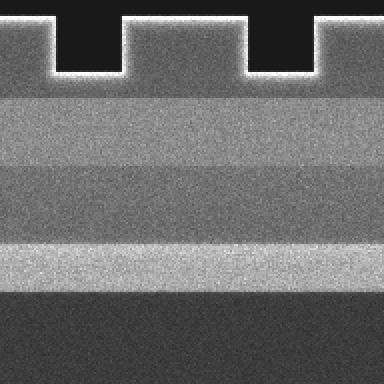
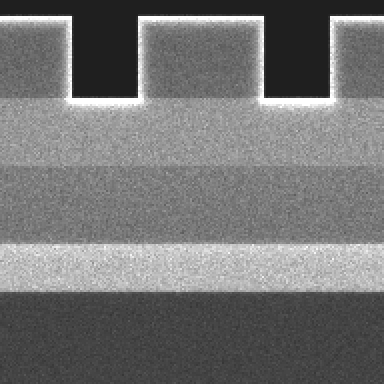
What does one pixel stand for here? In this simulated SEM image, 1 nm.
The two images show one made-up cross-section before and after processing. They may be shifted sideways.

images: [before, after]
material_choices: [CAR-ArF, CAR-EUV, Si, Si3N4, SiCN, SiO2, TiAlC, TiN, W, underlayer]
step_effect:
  removed: underlayer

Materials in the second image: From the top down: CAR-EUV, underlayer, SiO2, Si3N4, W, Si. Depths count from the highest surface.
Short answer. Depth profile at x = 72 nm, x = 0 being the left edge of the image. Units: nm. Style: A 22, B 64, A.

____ empty 82, SiO2 68, Si3N4 78, W 48, Si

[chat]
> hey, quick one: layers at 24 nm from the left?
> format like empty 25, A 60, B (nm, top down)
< CAR-EUV 56, underlayer 26, SiO2 68, Si3N4 78, W 48, Si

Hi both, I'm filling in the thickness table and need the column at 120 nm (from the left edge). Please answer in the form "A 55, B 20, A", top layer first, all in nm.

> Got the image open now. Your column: empty 82, SiO2 68, Si3N4 78, W 48, Si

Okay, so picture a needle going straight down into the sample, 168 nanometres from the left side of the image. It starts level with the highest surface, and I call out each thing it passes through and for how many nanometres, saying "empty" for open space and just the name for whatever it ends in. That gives CAR-EUV 56, underlayer 26, SiO2 68, Si3N4 78, W 48, Si